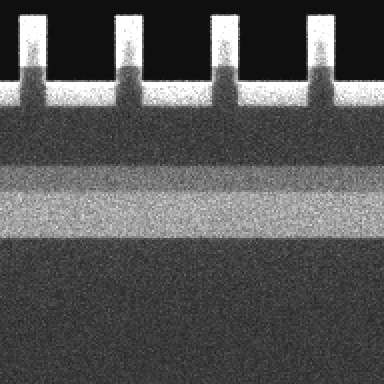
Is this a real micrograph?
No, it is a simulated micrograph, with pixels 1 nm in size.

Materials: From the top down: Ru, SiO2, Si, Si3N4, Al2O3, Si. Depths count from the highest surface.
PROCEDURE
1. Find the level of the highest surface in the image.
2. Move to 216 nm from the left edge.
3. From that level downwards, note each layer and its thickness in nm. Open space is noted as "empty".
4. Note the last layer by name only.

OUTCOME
Ru 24, SiO2 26, Si 100, Si3N4 26, Al2O3 46, Si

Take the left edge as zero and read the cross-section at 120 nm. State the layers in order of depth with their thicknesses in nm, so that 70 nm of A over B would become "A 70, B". Ru 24, SiO2 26, Si 100, Si3N4 26, Al2O3 46, Si